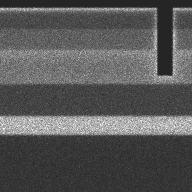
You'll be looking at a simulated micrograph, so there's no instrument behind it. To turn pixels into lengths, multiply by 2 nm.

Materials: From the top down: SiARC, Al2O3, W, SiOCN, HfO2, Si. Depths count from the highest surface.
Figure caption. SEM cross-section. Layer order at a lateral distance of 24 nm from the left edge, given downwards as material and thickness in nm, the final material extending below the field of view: SiARC 42, Al2O3 42, W 68, SiOCN 64, HfO2 38, Si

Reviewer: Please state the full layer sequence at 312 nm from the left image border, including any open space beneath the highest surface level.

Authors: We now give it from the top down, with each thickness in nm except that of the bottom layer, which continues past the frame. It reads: SiARC 42, Al2O3 42, W 68, SiOCN 64, HfO2 38, Si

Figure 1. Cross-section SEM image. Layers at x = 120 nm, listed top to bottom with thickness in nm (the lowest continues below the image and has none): SiARC 42, Al2O3 42, W 68, SiOCN 64, HfO2 38, Si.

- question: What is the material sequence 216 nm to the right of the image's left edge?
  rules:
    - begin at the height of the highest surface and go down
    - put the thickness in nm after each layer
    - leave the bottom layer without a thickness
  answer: SiARC 42, Al2O3 42, W 68, SiOCN 64, HfO2 38, Si